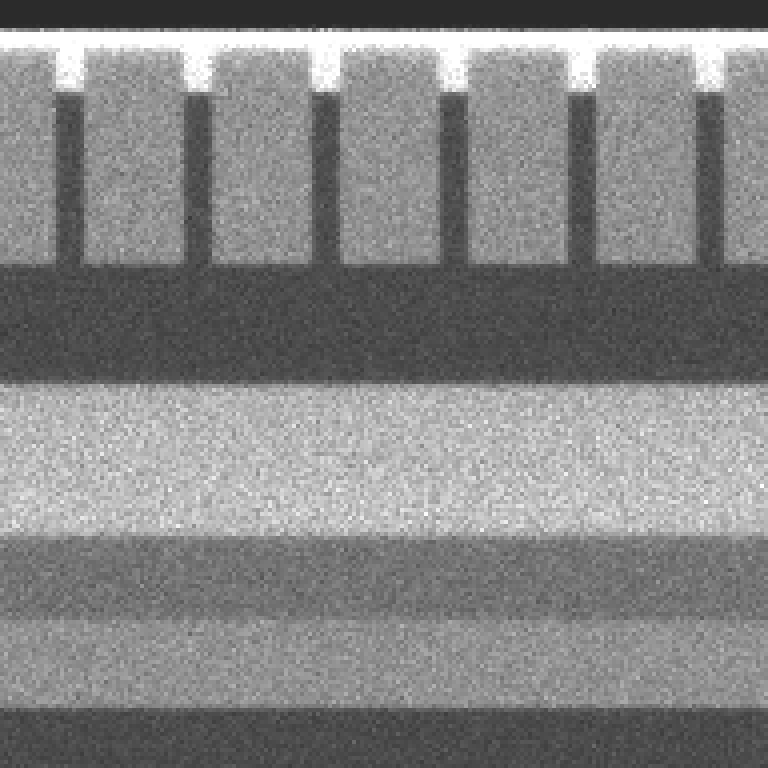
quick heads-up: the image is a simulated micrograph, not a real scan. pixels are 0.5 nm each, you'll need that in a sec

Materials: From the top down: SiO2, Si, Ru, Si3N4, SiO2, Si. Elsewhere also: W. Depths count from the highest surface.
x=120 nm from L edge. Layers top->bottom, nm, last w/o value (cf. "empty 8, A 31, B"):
SiO2 116, Si 60, Ru 76, Si3N4 42, SiO2 44, Si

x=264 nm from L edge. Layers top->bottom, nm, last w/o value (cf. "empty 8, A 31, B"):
SiO2 116, Si 60, Ru 76, Si3N4 42, SiO2 44, Si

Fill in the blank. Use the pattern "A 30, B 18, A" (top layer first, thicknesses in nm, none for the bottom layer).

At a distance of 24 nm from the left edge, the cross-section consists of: SiO2 116, Si 60, Ru 76, Si3N4 42, SiO2 44, Si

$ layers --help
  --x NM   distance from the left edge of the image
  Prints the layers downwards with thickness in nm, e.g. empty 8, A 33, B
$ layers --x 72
SiO2 116, Si 60, Ru 76, Si3N4 42, SiO2 44, Si